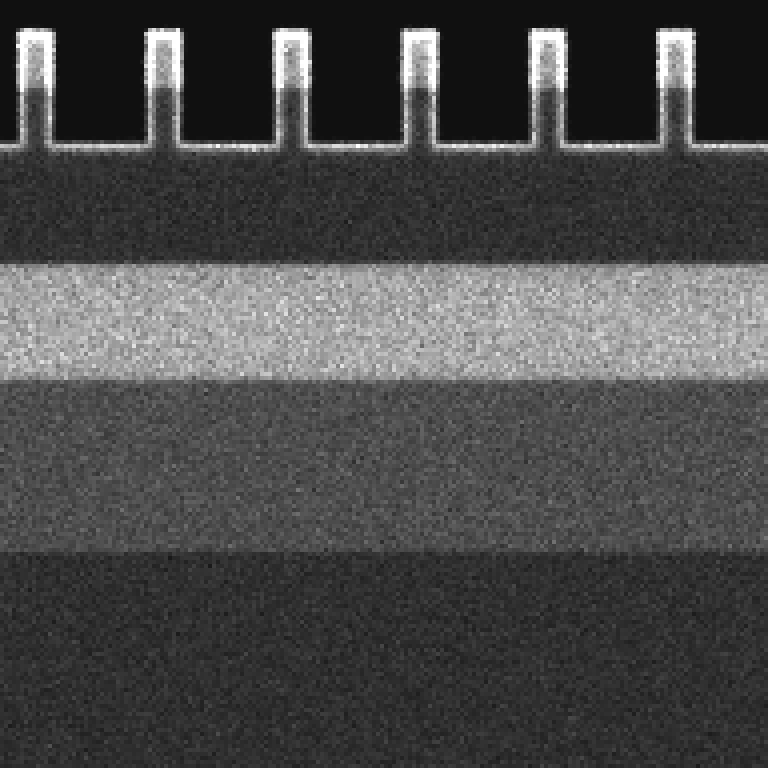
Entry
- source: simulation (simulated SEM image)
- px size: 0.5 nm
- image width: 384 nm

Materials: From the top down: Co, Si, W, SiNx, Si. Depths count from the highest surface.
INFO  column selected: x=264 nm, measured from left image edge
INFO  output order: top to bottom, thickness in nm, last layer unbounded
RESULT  empty 56, Si 60, W 58, SiNx 86, Si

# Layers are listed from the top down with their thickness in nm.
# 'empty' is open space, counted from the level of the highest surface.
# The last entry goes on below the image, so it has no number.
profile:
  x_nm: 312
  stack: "empty 56, Si 60, W 58, SiNx 86, Si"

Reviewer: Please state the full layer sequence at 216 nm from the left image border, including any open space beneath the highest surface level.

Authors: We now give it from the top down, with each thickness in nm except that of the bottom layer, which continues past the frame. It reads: Co 28, Si 88, W 58, SiNx 86, Si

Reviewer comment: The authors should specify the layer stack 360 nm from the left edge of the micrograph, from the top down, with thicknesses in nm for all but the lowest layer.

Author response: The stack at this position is empty 56, Si 60, W 58, SiNx 86, Si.